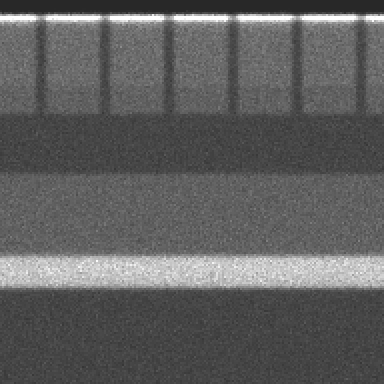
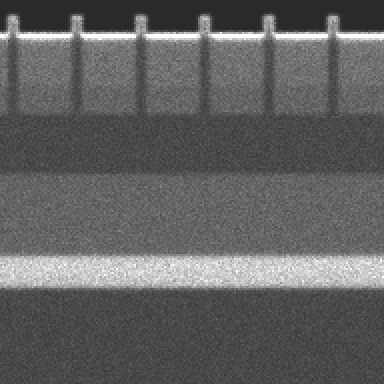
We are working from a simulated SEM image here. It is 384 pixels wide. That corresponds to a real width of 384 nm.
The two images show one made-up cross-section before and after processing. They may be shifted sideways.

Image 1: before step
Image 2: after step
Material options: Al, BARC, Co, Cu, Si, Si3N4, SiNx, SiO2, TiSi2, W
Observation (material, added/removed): Si3N4, removed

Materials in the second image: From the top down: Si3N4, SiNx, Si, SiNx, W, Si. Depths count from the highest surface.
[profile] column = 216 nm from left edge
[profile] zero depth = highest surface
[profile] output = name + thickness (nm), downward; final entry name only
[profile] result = empty 18, Si3N4 52, SiNx 28, Si 60, SiNx 82, W 32, Si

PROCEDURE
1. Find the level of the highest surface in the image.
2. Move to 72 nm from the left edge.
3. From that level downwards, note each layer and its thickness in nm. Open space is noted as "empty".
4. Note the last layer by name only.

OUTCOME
Si 158, SiNx 82, W 32, Si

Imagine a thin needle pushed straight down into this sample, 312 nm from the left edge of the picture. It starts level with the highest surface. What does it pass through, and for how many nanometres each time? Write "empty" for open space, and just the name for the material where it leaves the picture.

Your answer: empty 18, Si3N4 52, SiNx 28, Si 60, SiNx 82, W 32, Si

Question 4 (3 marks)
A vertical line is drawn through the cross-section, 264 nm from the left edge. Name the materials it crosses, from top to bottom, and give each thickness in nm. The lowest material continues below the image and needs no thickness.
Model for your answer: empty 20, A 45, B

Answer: Si 158, SiNx 82, W 32, Si